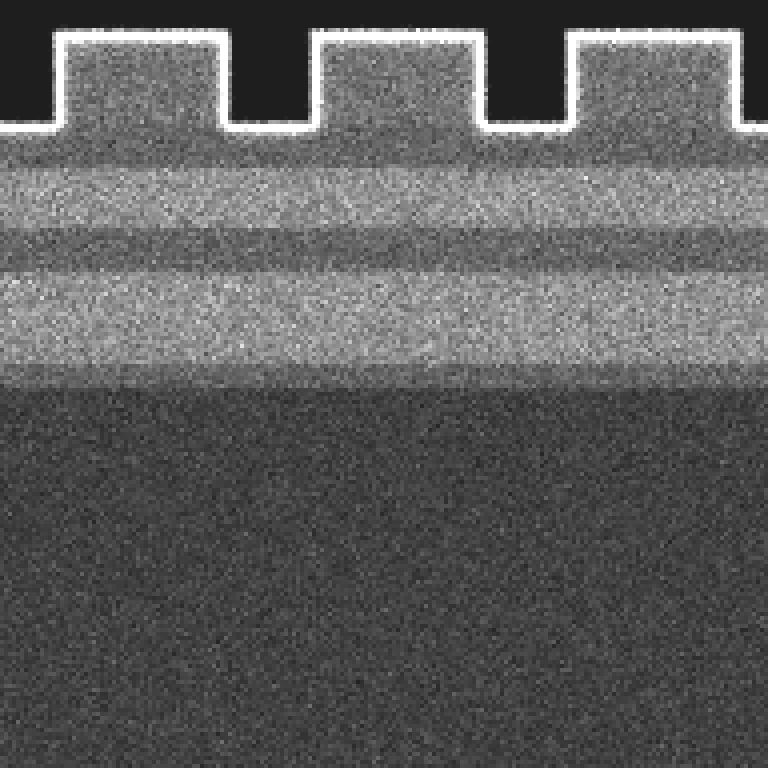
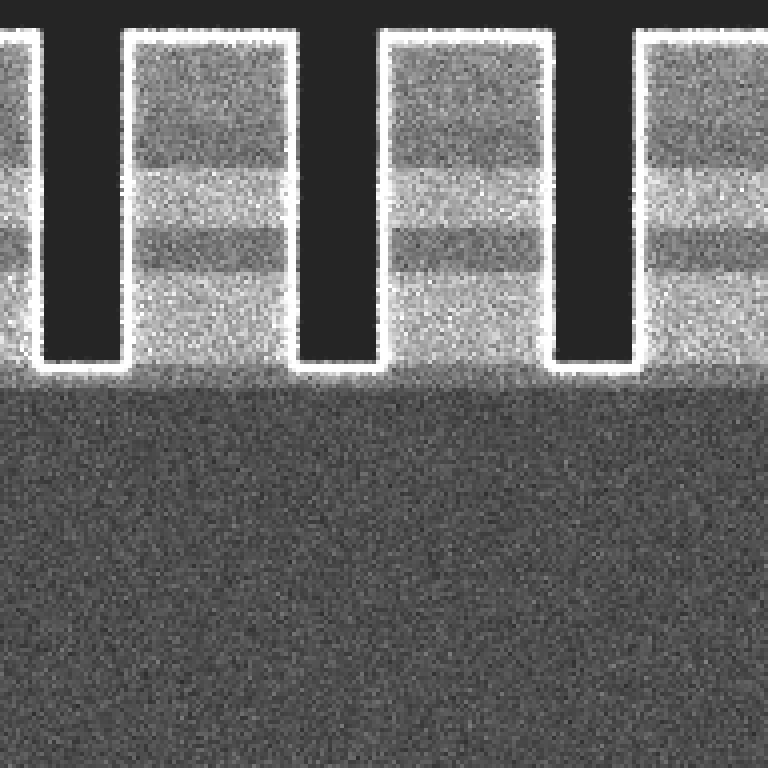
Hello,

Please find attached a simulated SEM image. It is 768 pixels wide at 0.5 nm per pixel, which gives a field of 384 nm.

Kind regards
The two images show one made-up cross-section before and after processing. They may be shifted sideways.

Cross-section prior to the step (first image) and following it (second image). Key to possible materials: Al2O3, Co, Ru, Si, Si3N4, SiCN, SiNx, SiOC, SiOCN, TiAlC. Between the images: Co and SiNx was removed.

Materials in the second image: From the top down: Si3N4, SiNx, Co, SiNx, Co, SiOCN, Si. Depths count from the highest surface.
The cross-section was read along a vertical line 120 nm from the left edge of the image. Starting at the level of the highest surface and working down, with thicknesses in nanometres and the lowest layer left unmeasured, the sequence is Si3N4 46, SiNx 22, Co 30, SiNx 22, Co 46, SiOCN 12, Si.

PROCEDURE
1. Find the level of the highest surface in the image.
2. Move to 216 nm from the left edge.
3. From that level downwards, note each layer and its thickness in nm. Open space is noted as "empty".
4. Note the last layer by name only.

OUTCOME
Si3N4 46, SiNx 22, Co 30, SiNx 22, Co 46, SiOCN 12, Si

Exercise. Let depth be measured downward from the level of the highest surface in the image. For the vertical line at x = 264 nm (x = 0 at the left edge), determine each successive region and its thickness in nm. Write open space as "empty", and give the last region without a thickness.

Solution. Si3N4 46, SiNx 22, Co 30, SiNx 22, Co 46, SiOCN 12, Si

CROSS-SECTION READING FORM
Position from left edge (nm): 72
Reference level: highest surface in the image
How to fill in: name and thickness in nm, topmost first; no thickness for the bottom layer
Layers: Si3N4 46, SiNx 22, Co 30, SiNx 22, Co 46, SiOCN 12, Si